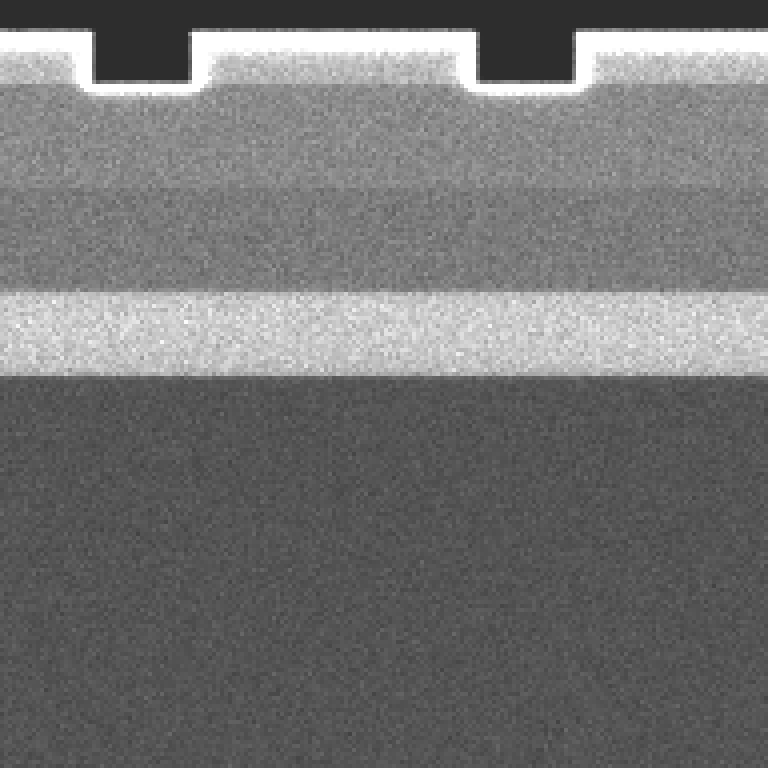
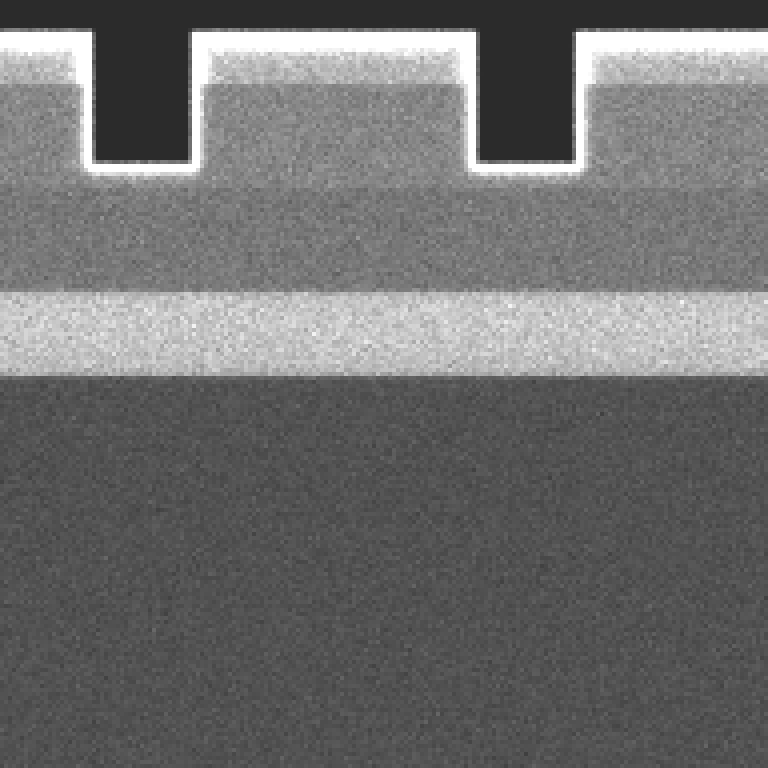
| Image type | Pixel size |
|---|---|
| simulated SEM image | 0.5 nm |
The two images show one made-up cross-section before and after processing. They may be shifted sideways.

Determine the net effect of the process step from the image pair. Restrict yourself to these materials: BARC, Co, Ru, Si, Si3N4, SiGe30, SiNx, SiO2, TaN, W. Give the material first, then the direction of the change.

Si3N4: removed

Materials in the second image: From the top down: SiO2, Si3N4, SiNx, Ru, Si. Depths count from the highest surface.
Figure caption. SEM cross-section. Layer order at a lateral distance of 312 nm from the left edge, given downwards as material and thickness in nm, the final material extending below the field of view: SiO2 26, Si3N4 52, SiNx 52, Ru 42, Si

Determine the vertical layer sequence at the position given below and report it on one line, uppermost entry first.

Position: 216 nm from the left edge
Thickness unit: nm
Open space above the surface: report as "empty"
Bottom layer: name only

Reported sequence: SiO2 26, Si3N4 52, SiNx 52, Ru 42, Si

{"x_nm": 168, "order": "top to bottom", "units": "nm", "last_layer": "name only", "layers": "SiO2 26, Si3N4 52, SiNx 52, Ru 42, Si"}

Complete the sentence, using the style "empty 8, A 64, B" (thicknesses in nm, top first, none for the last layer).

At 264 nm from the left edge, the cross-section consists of empty 66, Si3N4 12, SiNx 52, Ru 42, Si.